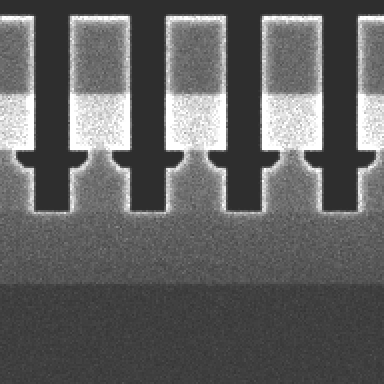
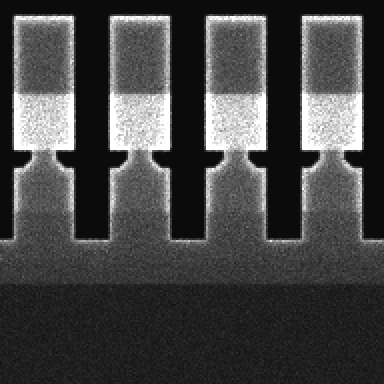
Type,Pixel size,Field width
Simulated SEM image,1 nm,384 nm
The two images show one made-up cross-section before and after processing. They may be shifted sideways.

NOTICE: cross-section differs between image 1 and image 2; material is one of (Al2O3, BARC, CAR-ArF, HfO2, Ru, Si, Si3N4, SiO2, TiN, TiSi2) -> removed: TiN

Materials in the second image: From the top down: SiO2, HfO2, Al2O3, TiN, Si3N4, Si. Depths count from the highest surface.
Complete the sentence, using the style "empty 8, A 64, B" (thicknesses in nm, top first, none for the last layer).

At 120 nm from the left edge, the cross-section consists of SiO2 78, HfO2 56, empty 16, Al2O3 46, TiN 52, Si3N4 20, Si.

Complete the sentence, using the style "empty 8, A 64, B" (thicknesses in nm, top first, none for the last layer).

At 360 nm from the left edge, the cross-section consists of SiO2 78, HfO2 56, empty 18, Al2O3 44, TiN 52, Si3N4 20, Si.